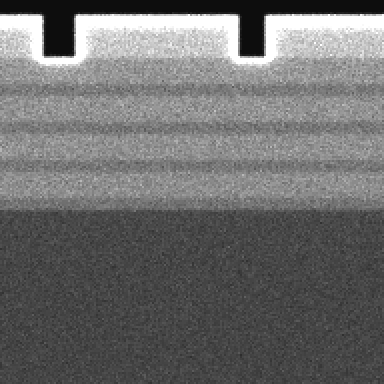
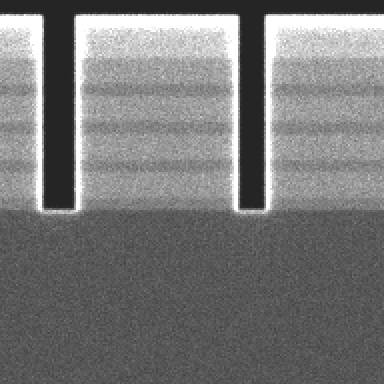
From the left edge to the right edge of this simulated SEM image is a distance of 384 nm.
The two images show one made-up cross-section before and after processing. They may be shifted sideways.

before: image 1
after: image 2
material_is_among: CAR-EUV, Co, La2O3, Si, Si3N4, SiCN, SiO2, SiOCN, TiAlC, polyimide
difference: Si3N4 and SiOCN, removed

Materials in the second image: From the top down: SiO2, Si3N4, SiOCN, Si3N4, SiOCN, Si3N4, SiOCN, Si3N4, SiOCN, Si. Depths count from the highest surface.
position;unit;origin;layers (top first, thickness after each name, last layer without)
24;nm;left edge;SiO2 42, Si3N4 26, SiOCN 12, Si3N4 26, SiOCN 12, Si3N4 26, SiOCN 12, Si3N4 26, SiOCN 12, Si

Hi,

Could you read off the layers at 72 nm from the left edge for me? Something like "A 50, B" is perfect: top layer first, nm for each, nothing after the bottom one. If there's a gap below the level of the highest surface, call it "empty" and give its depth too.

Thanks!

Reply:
empty 194, Si